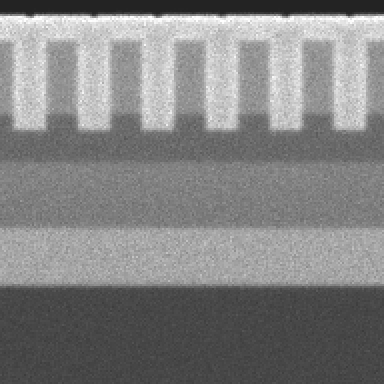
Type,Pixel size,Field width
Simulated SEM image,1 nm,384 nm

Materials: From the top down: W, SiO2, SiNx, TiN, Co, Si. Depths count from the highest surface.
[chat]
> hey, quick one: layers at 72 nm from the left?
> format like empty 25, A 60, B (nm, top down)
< W 24, SiO2 74, SiNx 48, TiN 66, Co 58, Si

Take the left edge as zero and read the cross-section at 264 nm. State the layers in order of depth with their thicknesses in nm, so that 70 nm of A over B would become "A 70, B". W 24, SiO2 74, SiNx 48, TiN 66, Co 58, Si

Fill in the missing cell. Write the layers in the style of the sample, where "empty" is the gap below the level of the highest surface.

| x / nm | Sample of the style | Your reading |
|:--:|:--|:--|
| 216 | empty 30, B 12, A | W 114, SiNx 32, TiN 66, Co 58, Si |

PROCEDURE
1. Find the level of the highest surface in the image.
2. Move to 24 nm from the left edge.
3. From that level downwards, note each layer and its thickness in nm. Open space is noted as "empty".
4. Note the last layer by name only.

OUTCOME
W 114, SiNx 32, TiN 66, Co 58, Si